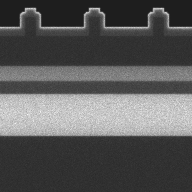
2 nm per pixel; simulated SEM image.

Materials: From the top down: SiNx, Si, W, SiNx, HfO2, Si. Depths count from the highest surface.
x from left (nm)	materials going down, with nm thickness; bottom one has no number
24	empty 38, SiNx 18, Si 60, W 30, SiNx 26, HfO2 84, Si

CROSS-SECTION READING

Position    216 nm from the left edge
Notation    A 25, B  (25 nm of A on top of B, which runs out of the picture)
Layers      empty 38, SiNx 18, Si 60, W 30, SiNx 26, HfO2 84, Si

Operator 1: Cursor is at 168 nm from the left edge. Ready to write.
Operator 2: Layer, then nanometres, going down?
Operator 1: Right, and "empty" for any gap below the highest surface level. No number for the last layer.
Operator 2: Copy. empty 12, SiNx 44, Si 60, W 30, SiNx 26, HfO2 84, Si